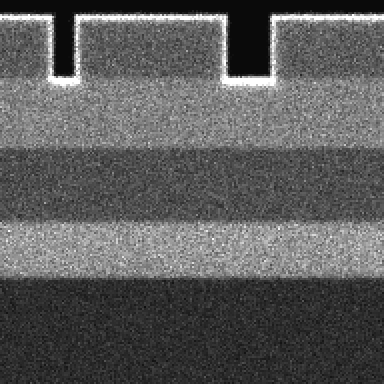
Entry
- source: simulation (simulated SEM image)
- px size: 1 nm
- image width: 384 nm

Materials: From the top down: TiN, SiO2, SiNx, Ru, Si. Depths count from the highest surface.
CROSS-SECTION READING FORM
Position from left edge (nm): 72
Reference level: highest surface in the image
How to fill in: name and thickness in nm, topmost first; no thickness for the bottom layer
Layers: empty 62, SiO2 70, SiNx 74, Ru 56, Si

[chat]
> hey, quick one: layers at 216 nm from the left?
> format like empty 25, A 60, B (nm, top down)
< TiN 62, SiO2 70, SiNx 74, Ru 56, Si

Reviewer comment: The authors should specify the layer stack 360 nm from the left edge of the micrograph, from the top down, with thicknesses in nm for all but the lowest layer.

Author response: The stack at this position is TiN 62, SiO2 70, SiNx 74, Ru 56, Si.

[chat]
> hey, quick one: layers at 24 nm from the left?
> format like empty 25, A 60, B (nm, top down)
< TiN 62, SiO2 70, SiNx 74, Ru 56, Si